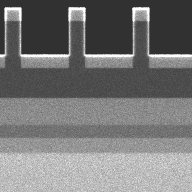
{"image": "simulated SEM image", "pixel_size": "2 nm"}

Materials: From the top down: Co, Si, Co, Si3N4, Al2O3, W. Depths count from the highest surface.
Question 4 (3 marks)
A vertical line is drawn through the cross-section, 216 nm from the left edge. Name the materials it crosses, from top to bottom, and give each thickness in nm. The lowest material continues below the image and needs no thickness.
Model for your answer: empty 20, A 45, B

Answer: empty 94, Co 26, Si 60, Co 54, Si3N4 26, Al2O3 30, W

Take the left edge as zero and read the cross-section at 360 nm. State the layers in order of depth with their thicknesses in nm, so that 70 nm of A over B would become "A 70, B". empty 94, Co 26, Si 60, Co 54, Si3N4 26, Al2O3 30, W